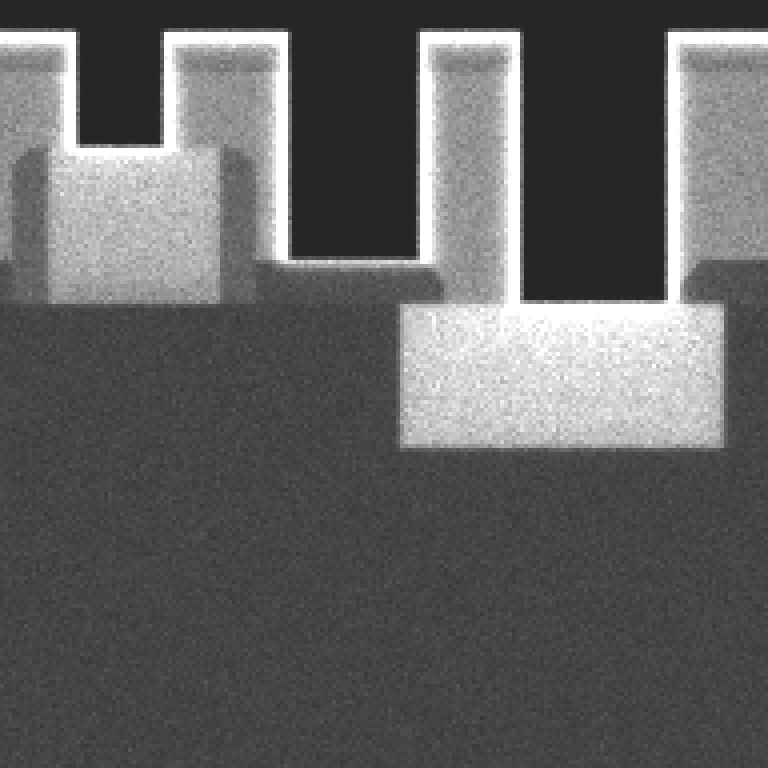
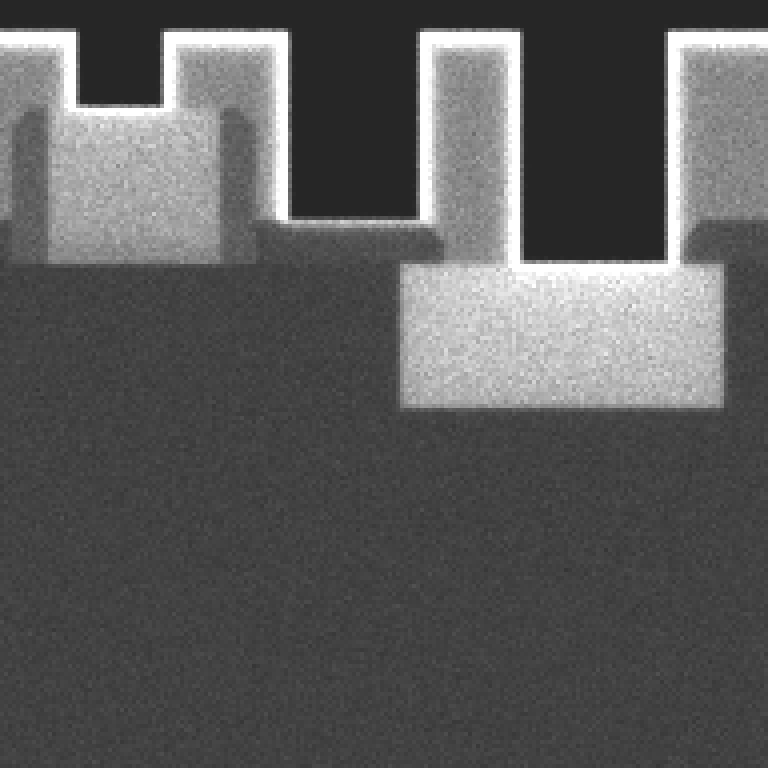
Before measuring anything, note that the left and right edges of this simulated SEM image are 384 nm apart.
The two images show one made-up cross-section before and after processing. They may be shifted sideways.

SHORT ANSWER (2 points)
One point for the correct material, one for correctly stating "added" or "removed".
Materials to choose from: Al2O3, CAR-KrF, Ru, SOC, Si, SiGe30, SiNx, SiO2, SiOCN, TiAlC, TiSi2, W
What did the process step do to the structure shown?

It removed SOC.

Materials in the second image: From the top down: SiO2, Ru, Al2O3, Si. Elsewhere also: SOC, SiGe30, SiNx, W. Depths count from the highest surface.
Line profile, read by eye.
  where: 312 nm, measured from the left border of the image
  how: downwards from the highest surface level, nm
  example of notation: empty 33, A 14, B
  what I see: empty 116, W 72, Si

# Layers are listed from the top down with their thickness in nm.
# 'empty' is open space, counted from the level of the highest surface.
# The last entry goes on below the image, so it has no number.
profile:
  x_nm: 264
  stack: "empty 116, W 72, Si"